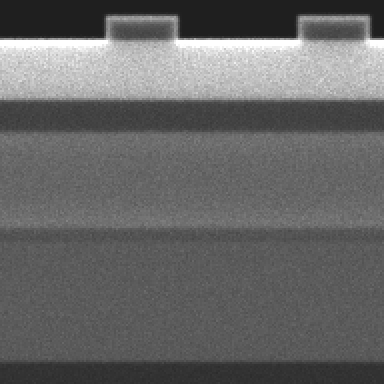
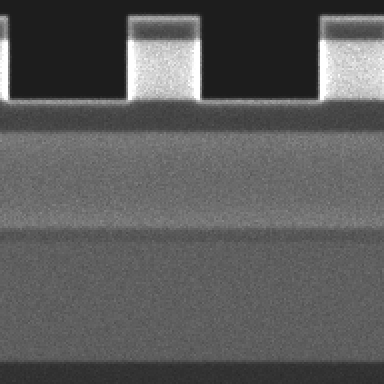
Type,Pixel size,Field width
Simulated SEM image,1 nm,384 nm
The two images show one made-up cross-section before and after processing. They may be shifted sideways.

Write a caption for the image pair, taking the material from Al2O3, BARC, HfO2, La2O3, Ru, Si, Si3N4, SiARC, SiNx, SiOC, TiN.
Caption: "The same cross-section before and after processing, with HfO2 removed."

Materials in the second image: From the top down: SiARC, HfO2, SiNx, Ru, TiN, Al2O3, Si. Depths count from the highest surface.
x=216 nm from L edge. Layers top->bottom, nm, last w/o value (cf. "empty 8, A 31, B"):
empty 84, SiNx 32, Ru 96, TiN 14, Al2O3 120, Si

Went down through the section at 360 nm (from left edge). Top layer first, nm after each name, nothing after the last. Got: SiARC 24, HfO2 60, SiNx 32, Ru 96, TiN 14, Al2O3 120, Si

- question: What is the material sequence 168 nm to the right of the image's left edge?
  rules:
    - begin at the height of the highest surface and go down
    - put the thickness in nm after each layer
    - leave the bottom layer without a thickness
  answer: SiARC 24, HfO2 60, SiNx 32, Ru 96, TiN 14, Al2O3 120, Si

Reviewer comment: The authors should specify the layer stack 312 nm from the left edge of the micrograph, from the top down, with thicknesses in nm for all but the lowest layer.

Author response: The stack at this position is empty 84, SiNx 32, Ru 96, TiN 14, Al2O3 120, Si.